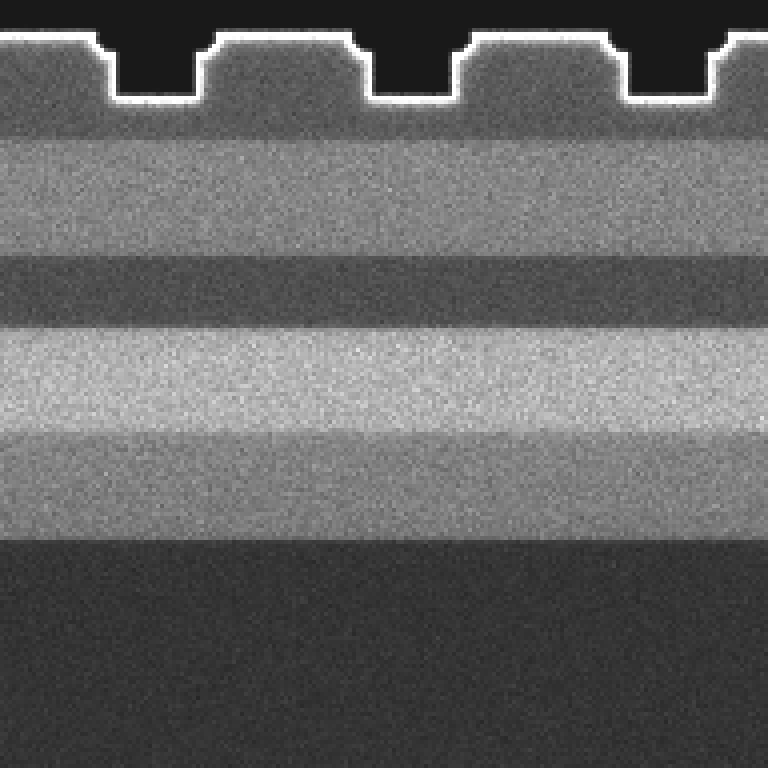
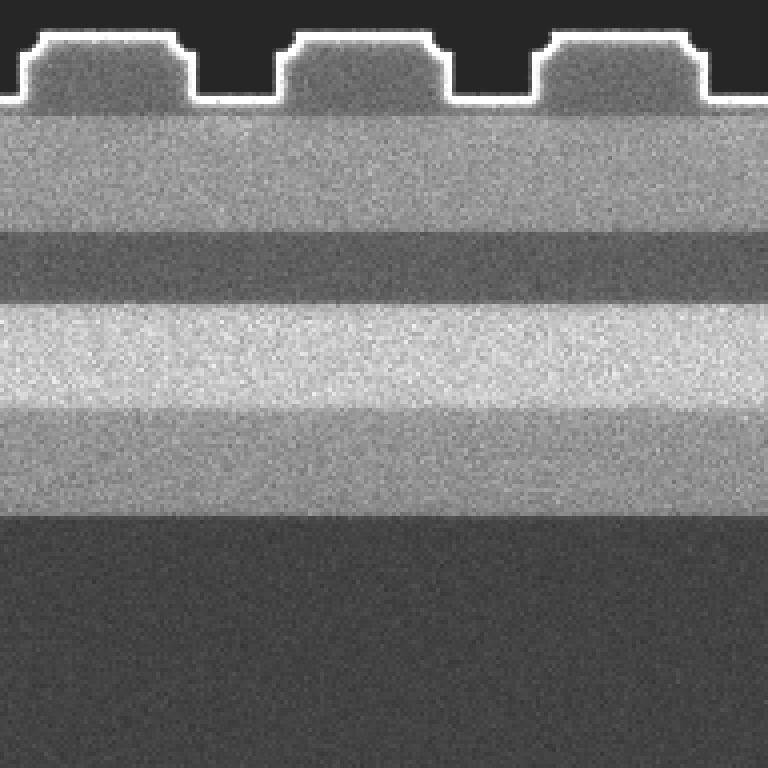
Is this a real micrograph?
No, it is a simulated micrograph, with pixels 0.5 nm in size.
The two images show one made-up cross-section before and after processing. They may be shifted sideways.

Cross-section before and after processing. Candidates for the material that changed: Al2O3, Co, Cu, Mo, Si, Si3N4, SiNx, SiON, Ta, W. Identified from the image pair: Si3N4 (removed).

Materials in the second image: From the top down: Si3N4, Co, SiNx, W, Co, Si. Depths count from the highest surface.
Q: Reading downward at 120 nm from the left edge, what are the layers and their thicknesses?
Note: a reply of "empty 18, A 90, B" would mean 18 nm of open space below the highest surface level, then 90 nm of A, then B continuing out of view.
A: empty 32, Si3N4 10, Co 58, SiNx 36, W 52, Co 54, Si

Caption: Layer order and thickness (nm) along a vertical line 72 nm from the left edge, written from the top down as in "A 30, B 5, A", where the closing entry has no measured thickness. Si3N4 42, Co 58, SiNx 36, W 52, Co 54, Si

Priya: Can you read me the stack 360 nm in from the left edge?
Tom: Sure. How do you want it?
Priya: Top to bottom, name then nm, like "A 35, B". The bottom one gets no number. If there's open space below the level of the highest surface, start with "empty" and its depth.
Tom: empty 32, Si3N4 10, Co 58, SiNx 36, W 52, Co 54, Si